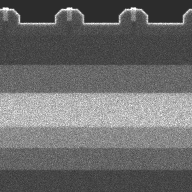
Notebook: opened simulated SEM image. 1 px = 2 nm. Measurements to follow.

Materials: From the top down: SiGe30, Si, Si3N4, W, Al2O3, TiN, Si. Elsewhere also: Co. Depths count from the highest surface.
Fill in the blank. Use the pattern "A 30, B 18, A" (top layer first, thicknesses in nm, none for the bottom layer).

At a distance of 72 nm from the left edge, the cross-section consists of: empty 30, SiGe30 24, Si 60, Si3N4 56, W 68, Al2O3 42, TiN 44, Si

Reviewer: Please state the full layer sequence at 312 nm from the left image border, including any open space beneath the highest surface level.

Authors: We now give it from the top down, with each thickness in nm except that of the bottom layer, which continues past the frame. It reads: empty 30, SiGe30 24, Si 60, Si3N4 56, W 68, Al2O3 42, TiN 44, Si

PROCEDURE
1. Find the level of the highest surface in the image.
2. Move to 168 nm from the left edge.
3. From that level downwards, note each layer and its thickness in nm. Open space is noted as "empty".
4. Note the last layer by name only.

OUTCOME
empty 30, SiGe30 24, Si 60, Si3N4 56, W 68, Al2O3 42, TiN 44, Si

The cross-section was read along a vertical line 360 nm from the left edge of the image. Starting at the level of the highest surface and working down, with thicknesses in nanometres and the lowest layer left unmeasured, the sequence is empty 30, SiGe30 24, Si 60, Si3N4 56, W 68, Al2O3 42, TiN 44, Si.